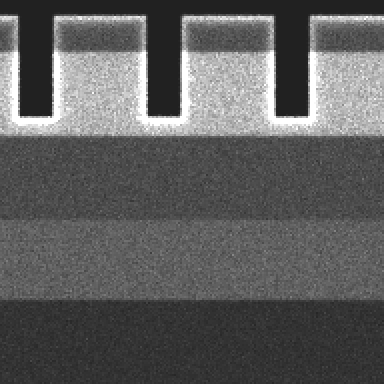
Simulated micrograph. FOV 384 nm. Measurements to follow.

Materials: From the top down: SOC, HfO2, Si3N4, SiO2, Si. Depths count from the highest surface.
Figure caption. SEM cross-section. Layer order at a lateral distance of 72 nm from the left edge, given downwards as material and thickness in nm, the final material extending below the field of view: SOC 36, HfO2 84, Si3N4 84, SiO2 80, Si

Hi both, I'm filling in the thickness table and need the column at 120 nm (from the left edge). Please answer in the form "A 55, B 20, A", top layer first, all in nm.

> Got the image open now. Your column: SOC 36, HfO2 84, Si3N4 84, SiO2 80, Si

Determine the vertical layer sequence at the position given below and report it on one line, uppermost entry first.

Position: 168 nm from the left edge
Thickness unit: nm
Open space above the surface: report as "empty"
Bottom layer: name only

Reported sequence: empty 102, HfO2 18, Si3N4 84, SiO2 80, Si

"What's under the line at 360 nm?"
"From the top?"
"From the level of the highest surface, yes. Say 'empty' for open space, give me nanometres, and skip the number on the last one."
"SOC 36, HfO2 84, Si3N4 84, SiO2 80, Si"